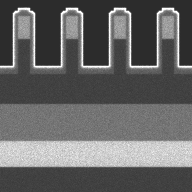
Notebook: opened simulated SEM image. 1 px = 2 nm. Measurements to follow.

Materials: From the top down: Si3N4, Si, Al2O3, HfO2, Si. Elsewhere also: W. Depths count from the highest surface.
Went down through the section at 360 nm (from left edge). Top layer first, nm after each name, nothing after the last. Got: empty 116, Si3N4 16, Si 60, Al2O3 74, HfO2 52, Si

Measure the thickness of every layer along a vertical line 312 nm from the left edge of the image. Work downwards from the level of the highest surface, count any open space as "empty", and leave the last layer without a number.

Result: empty 116, Si3N4 16, Si 60, Al2O3 74, HfO2 52, Si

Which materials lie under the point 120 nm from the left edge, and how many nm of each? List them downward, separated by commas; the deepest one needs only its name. empty 116, Si3N4 16, Si 60, Al2O3 74, HfO2 52, Si